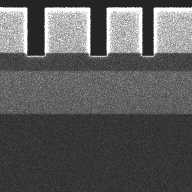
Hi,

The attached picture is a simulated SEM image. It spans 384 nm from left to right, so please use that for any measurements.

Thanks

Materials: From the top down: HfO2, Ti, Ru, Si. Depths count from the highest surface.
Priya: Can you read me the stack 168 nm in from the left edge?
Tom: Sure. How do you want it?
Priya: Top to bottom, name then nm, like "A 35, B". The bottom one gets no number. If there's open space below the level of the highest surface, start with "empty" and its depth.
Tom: HfO2 90, Ti 36, Ru 86, Si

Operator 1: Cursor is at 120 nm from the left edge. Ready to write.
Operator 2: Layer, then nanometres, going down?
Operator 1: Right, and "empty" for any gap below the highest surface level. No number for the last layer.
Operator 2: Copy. HfO2 90, Ti 36, Ru 86, Si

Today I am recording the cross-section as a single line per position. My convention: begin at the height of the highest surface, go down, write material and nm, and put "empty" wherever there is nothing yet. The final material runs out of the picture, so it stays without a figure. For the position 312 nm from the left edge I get HfO2 90, Ti 36, Ru 86, Si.